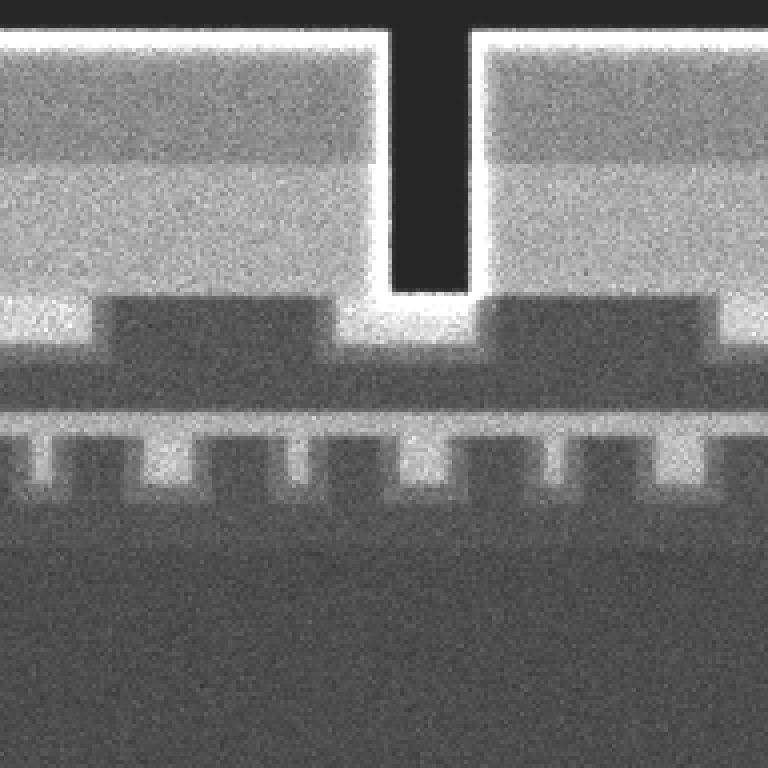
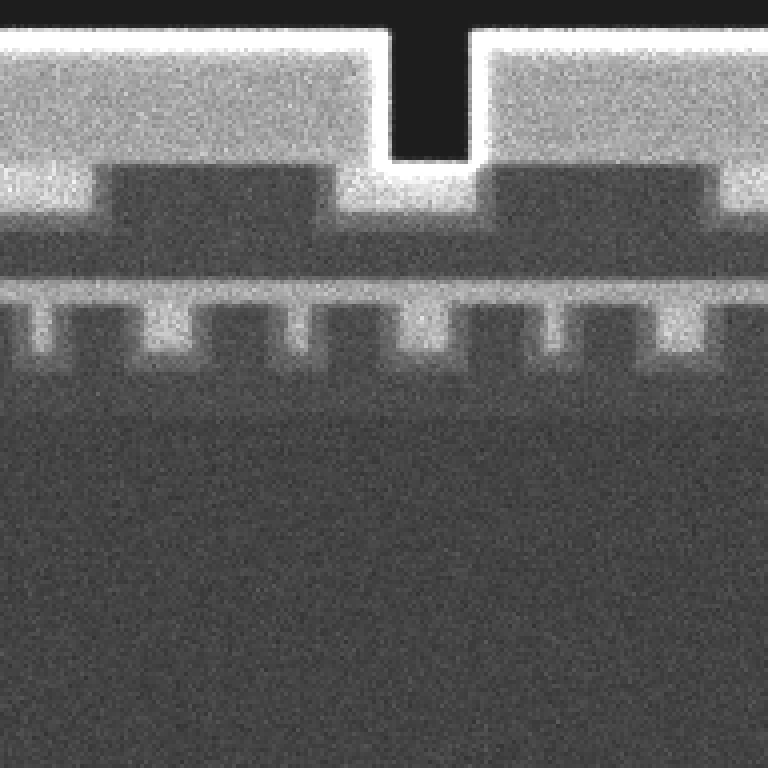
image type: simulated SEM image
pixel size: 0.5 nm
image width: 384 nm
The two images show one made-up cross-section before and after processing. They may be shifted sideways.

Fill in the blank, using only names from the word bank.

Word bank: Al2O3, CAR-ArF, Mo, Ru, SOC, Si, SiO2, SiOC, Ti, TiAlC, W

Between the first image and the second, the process removed SOC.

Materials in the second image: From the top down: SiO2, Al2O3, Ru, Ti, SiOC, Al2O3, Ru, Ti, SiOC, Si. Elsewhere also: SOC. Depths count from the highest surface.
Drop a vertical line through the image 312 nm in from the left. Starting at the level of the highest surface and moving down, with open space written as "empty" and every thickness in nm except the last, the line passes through SiO2 56, Al2O3 10, SiOC 58, Al2O3 12, SiOC 56, Si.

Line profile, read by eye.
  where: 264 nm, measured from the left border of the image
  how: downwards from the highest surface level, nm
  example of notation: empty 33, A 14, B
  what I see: SiO2 56, Al2O3 10, SiOC 58, Al2O3 12, Ti 34, SiOC 22, Si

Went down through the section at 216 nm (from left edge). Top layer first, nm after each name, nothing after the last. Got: empty 66, Ru 24, Ti 10, SiOC 24, Al2O3 12, Ru 24, Ti 10, SiOC 22, Si